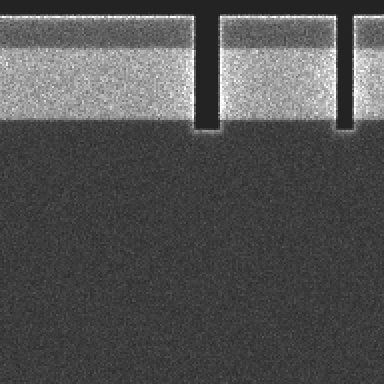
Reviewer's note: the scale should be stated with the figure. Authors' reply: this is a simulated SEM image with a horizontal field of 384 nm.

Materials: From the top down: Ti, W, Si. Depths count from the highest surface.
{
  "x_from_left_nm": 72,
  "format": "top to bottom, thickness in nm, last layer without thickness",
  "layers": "Ti 32, W 72, Si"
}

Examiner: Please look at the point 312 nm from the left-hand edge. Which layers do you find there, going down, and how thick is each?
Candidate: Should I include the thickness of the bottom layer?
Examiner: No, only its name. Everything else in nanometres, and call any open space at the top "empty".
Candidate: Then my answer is Ti 32, W 72, Si